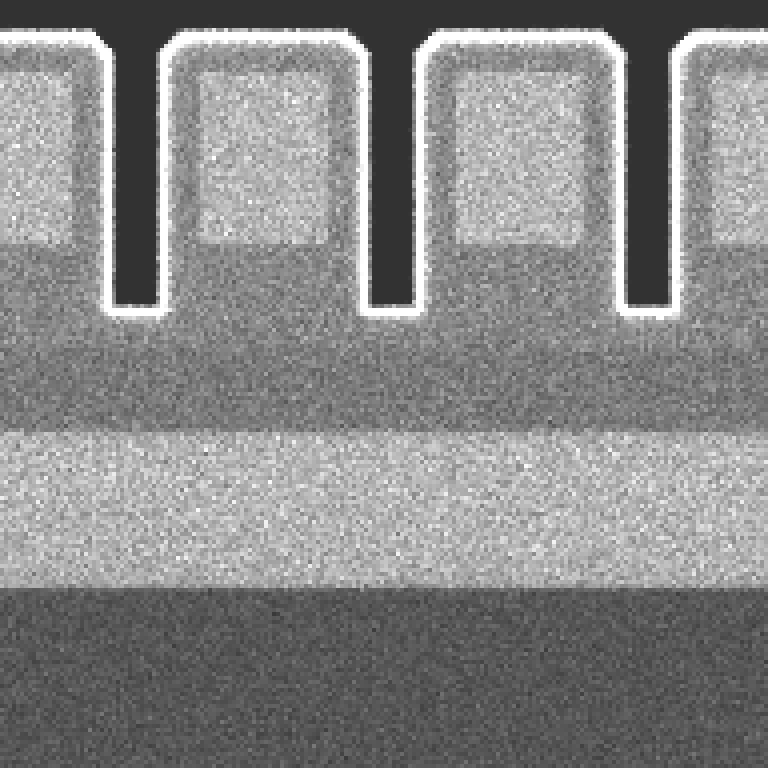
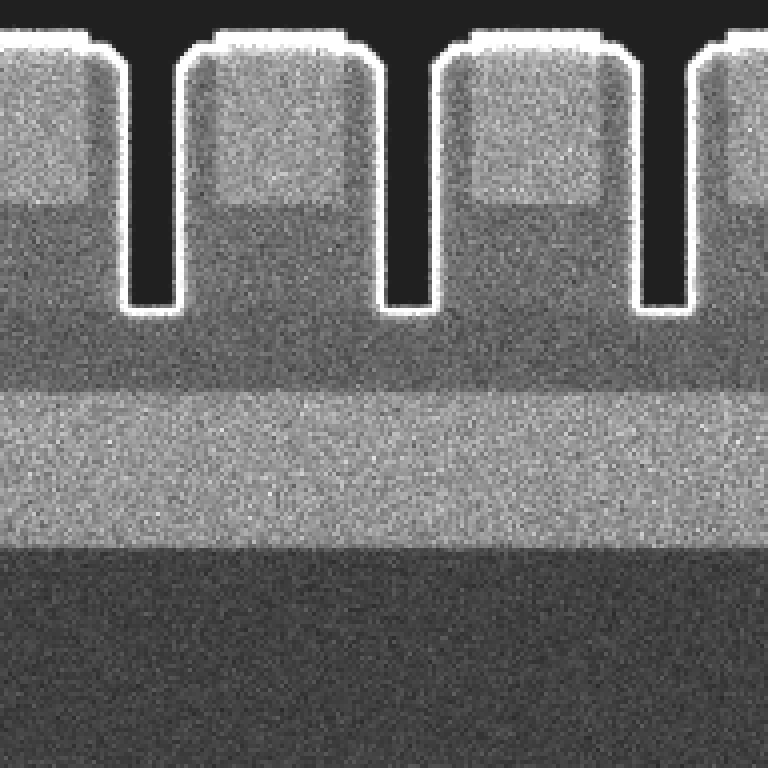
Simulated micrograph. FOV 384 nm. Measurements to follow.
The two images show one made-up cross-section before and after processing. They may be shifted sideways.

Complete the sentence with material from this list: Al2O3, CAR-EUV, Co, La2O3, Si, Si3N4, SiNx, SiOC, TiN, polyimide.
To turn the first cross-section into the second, Si3N4 must be removed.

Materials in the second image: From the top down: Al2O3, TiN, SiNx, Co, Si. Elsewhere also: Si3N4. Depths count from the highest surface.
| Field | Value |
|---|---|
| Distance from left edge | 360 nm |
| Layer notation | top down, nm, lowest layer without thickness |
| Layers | empty 6, Si3N4 132, SiNx 42, Co 78, Si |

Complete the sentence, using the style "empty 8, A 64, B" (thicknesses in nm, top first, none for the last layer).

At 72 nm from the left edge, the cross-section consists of empty 138, SiNx 42, Co 78, Si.